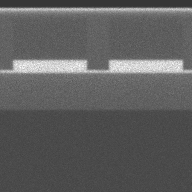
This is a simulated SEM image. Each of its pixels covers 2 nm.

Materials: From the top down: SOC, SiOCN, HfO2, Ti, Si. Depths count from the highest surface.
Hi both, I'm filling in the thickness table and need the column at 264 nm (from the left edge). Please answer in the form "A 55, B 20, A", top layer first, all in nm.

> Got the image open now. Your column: SOC 16, SiOCN 88, HfO2 26, Ti 74, Si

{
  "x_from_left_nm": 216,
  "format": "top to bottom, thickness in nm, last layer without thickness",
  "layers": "SOC 124, HfO2 6, Ti 74, Si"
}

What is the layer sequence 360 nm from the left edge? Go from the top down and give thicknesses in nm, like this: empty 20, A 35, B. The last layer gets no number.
SOC 16, SiOCN 88, HfO2 26, Ti 74, Si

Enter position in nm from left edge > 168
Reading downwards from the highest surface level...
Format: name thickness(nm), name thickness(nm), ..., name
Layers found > SOC 16, SiOCN 88, HfO2 26, Ti 74, Si